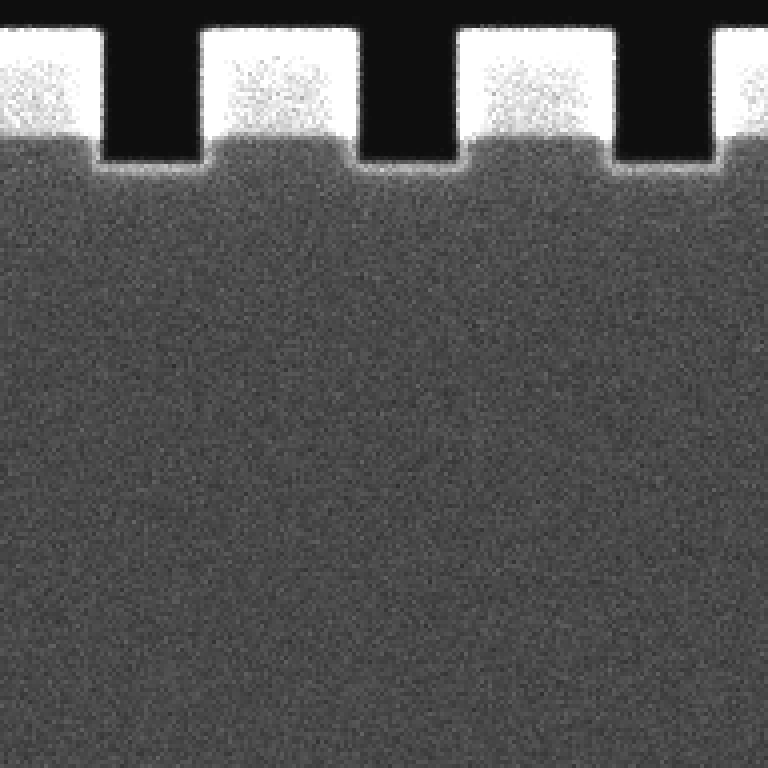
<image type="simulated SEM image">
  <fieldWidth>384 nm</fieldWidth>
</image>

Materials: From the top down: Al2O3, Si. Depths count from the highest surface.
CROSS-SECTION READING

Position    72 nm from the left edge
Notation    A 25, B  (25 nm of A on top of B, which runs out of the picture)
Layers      empty 66, Si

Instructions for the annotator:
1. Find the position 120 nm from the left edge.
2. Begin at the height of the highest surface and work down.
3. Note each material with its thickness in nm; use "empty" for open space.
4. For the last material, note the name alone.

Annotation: Al2O3 52, Si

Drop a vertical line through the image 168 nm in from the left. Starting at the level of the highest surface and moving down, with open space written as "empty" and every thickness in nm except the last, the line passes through Al2O3 52, Si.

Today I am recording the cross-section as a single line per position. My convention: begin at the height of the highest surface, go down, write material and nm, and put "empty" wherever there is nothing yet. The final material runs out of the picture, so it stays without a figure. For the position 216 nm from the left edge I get empty 66, Si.